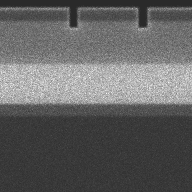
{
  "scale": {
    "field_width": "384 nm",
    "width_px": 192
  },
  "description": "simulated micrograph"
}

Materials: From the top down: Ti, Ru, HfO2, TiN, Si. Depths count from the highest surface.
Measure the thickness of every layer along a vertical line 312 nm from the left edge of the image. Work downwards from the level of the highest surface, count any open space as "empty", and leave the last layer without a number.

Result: Ti 26, Ru 86, HfO2 80, TiN 24, Si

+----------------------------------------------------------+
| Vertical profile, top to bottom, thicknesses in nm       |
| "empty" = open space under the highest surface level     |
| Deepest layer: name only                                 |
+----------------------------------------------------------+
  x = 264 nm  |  Ti 26, Ru 86, HfO2 80, TiN 24, Si